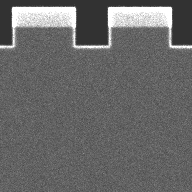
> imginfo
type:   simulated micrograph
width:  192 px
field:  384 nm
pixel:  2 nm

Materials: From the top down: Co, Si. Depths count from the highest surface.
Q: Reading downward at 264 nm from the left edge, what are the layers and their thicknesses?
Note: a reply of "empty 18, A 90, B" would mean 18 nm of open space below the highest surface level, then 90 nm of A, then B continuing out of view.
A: Co 38, Si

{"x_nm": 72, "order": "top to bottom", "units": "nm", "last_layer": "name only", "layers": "Co 38, Si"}